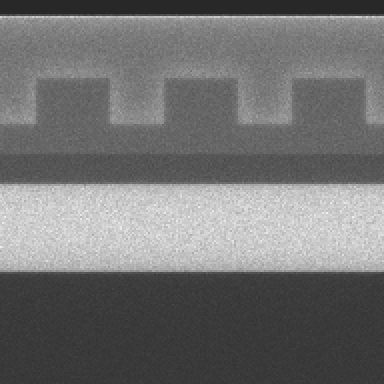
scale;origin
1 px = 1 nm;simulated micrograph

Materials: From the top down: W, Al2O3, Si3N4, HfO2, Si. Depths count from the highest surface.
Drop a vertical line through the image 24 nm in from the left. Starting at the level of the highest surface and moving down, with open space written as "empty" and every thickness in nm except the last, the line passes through W 108, Al2O3 30, Si3N4 30, HfO2 88, Si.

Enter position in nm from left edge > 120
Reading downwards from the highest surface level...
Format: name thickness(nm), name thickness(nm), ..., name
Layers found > W 108, Al2O3 30, Si3N4 30, HfO2 88, Si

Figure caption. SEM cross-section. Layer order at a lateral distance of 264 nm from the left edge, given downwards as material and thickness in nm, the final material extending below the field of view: W 108, Al2O3 30, Si3N4 30, HfO2 88, Si